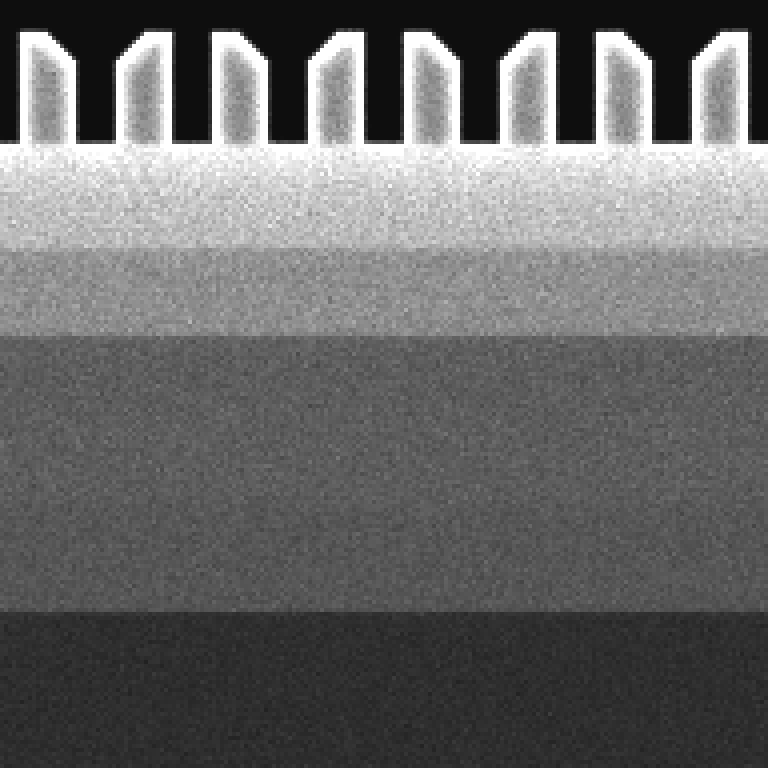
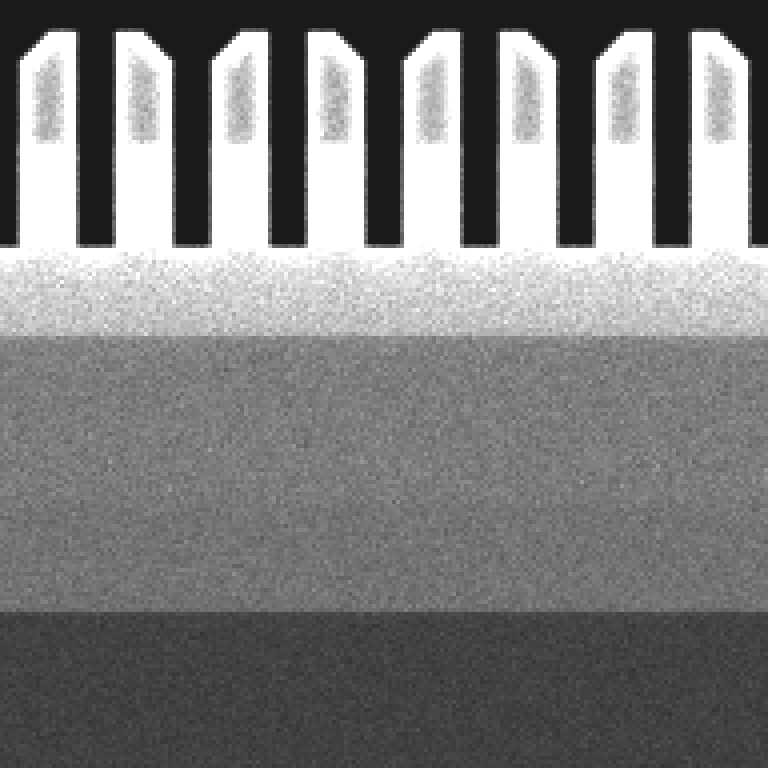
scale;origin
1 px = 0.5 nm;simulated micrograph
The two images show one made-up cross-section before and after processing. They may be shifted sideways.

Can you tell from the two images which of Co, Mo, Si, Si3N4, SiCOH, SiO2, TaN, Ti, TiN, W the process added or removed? Yes, it removed W.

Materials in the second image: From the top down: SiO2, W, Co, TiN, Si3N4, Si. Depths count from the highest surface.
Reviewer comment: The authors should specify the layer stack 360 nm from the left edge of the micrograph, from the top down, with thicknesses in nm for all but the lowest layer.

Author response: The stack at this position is empty 2, SiO2 54, W 52, Co 44, TiN 84, Si3N4 54, Si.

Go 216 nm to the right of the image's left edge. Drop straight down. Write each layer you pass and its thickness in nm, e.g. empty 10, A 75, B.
SiO2 56, W 52, Co 44, TiN 84, Si3N4 54, Si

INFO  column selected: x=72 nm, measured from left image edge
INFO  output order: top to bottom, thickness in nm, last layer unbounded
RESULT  empty 2, SiO2 54, W 52, Co 44, TiN 84, Si3N4 54, Si